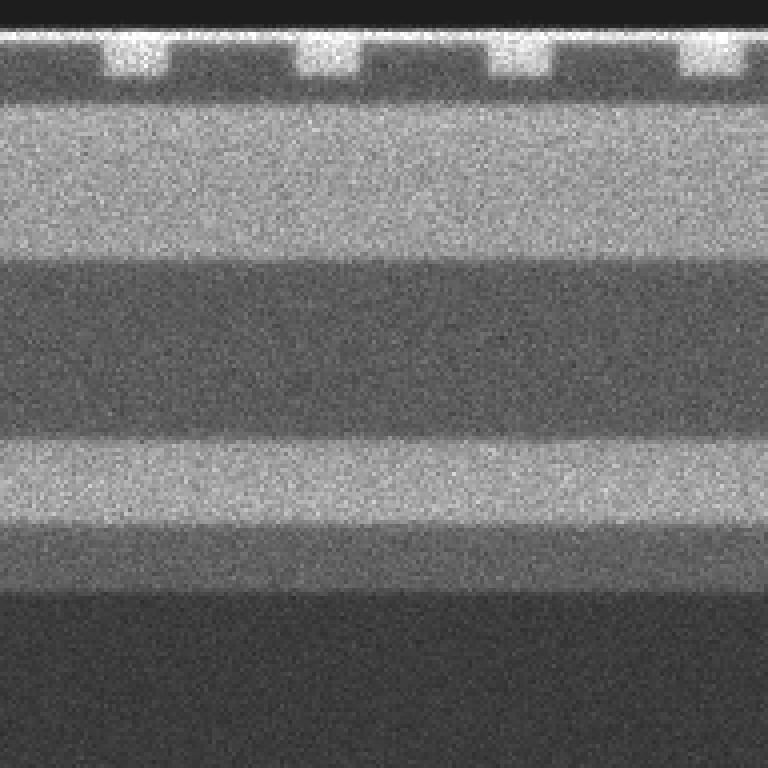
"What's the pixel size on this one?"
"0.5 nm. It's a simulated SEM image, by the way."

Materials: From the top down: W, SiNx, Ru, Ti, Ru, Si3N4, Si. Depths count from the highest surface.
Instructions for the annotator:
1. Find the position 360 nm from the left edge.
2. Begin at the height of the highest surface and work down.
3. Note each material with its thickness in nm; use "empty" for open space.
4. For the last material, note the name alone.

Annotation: W 22, SiNx 14, Ru 78, Ti 90, Ru 42, Si3N4 34, Si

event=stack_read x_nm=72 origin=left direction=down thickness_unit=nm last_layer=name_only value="W 22, SiNx 14, Ru 78, Ti 90, Ru 42, Si3N4 34, Si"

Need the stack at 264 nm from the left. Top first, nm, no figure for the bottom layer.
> W 22, SiNx 14, Ru 78, Ti 90, Ru 42, Si3N4 34, Si